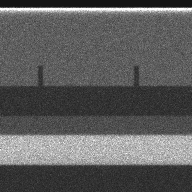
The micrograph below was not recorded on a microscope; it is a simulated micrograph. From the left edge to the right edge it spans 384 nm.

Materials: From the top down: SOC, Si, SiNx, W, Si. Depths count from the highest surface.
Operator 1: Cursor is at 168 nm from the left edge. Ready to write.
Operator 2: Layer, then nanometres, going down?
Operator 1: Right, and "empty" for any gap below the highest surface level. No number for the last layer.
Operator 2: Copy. SOC 156, Si 60, SiNx 38, W 60, Si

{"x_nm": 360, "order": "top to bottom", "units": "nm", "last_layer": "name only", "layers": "SOC 156, Si 60, SiNx 38, W 60, Si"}